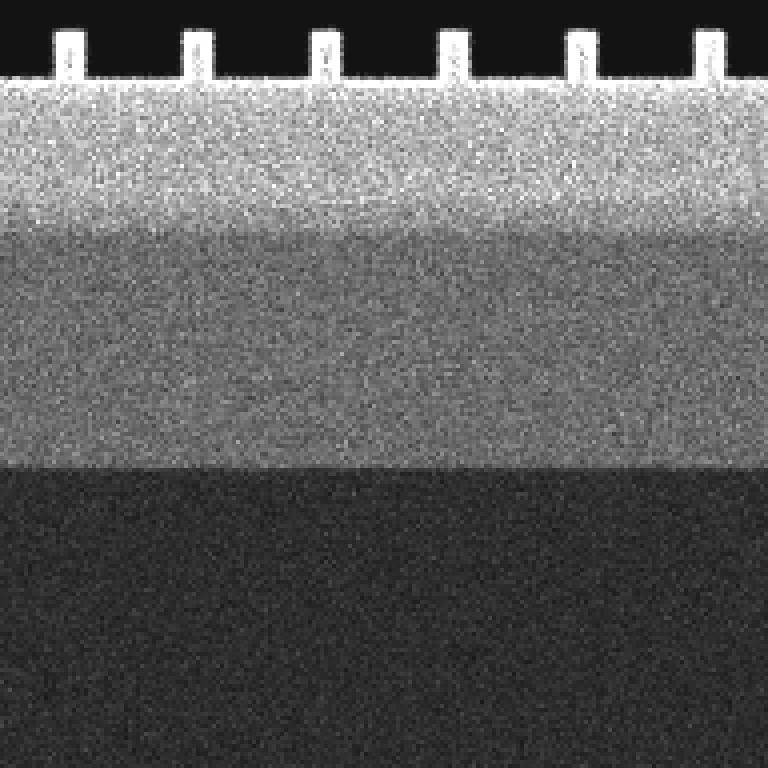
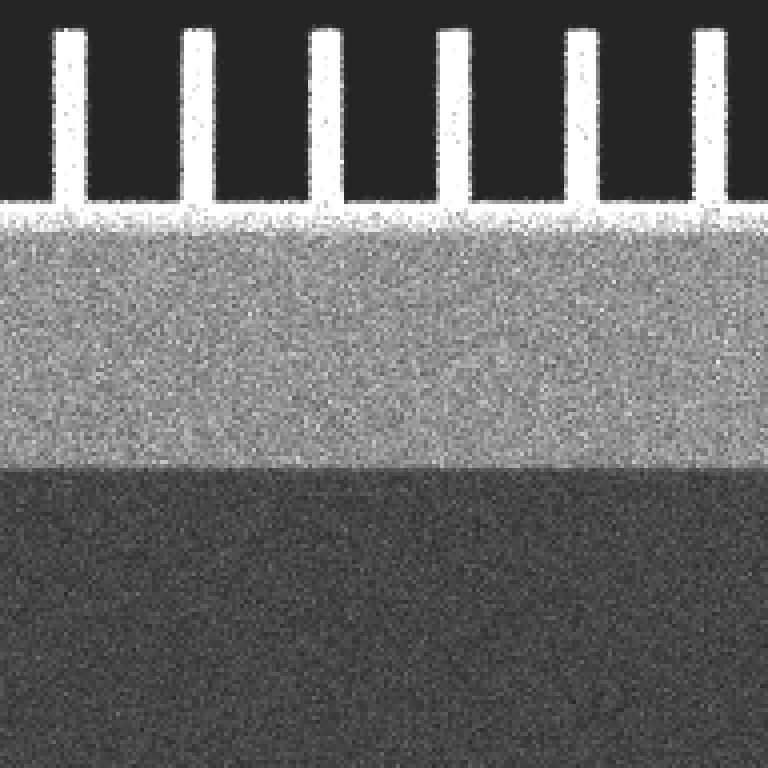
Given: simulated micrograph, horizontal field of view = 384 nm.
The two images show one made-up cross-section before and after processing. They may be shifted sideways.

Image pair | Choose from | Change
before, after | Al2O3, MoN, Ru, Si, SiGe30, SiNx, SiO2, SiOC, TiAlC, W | W (removed)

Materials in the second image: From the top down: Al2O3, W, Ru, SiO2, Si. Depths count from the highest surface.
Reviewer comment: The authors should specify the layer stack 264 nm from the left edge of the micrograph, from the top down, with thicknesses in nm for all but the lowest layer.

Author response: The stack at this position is empty 86, Ru 14, SiO2 118, Si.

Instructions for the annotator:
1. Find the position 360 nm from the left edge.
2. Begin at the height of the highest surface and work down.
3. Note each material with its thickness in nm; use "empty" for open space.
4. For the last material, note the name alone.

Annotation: Al2O3 24, W 62, Ru 14, SiO2 118, Si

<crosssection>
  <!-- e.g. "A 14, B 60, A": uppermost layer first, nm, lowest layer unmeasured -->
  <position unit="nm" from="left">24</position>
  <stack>empty 86, Ru 14, SiO2 118, Si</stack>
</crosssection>